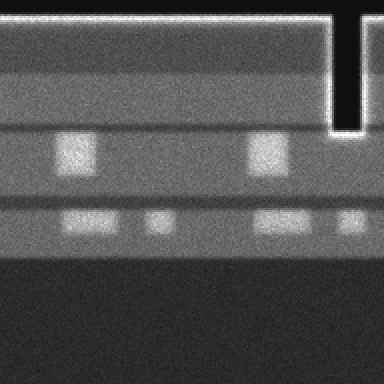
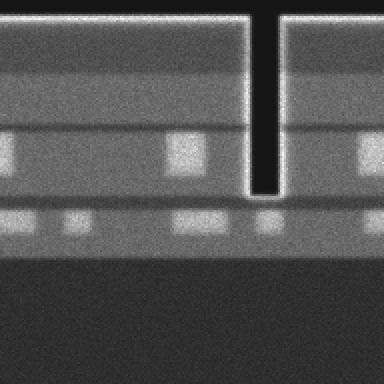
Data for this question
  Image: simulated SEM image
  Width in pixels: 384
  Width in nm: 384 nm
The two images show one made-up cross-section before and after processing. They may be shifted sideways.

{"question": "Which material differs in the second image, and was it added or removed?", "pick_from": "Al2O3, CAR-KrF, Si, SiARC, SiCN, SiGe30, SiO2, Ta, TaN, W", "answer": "SiO2, removed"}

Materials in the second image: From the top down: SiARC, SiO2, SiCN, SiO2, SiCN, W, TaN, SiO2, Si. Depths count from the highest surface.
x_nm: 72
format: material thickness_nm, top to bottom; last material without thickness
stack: SiARC 58, SiO2 50, SiCN 8, SiO2 64, SiCN 14, W 18, TaN 6, SiO2 24, Si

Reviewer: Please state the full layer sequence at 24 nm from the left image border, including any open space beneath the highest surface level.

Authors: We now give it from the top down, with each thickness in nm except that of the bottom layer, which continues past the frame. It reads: SiARC 58, SiO2 50, SiCN 8, SiO2 64, SiCN 14, W 18, TaN 6, SiO2 24, Si